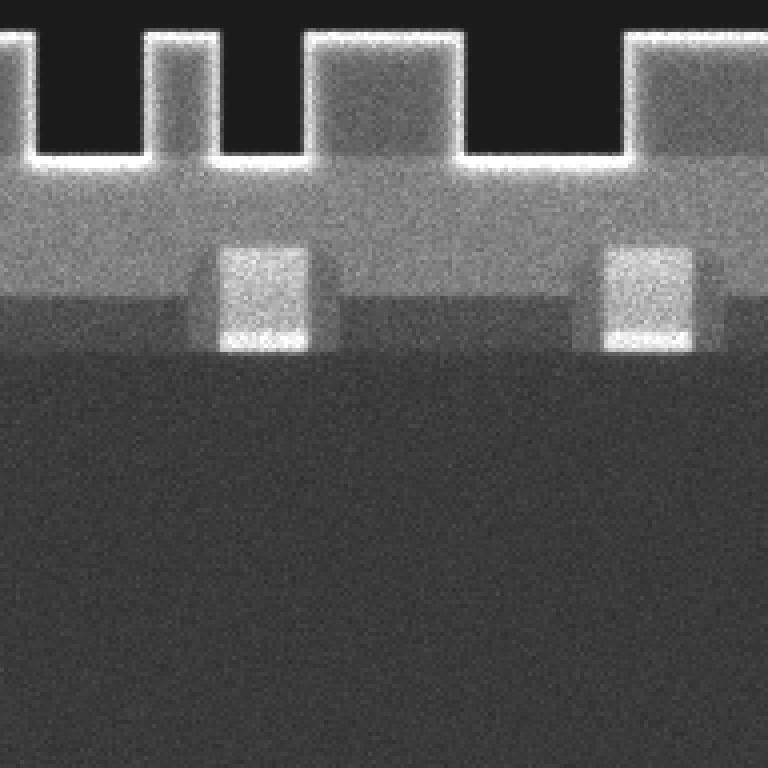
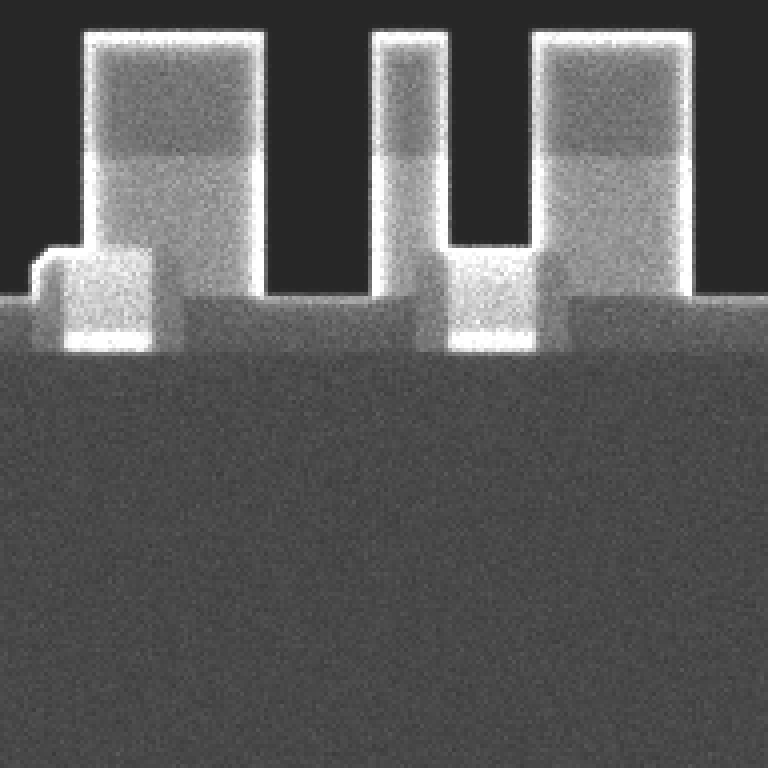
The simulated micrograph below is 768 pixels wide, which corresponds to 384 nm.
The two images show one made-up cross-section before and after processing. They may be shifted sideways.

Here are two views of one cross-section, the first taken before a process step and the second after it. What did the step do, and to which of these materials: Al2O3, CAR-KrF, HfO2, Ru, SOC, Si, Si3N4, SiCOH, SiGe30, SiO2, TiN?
It removed SiO2.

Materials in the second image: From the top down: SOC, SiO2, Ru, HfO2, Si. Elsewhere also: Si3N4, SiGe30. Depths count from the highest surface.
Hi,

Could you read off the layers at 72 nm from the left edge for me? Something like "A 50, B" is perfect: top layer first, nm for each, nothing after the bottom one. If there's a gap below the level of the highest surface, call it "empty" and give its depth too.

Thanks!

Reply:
SOC 62, SiO2 46, Ru 42, HfO2 10, Si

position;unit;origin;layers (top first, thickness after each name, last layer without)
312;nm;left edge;SOC 62, SiO2 70, SiGe30 28, Si